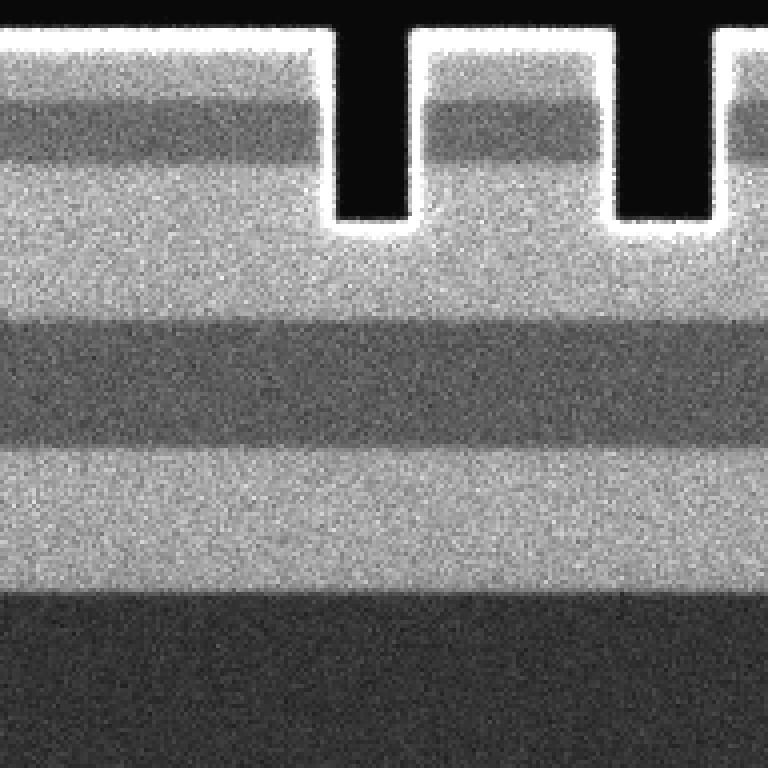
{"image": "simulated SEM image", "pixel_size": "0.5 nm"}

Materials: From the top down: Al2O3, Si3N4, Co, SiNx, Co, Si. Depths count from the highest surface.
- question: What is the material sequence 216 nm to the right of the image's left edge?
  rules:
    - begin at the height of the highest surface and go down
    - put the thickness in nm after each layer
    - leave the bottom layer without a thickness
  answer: Al2O3 34, Si3N4 32, Co 78, SiNx 64, Co 72, Si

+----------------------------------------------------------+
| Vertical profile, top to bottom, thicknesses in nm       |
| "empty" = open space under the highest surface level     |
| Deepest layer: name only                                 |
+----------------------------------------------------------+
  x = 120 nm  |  Al2O3 34, Si3N4 32, Co 78, SiNx 64, Co 72, Si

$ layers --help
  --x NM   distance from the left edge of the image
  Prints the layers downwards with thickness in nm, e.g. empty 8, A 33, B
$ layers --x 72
Al2O3 34, Si3N4 32, Co 78, SiNx 64, Co 72, Si